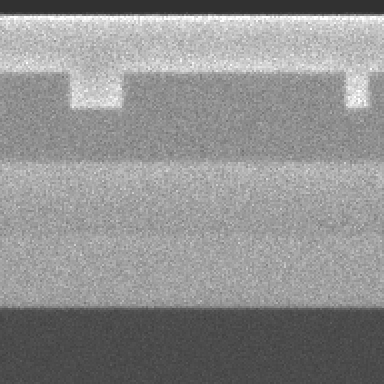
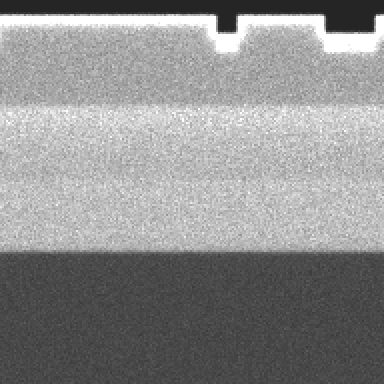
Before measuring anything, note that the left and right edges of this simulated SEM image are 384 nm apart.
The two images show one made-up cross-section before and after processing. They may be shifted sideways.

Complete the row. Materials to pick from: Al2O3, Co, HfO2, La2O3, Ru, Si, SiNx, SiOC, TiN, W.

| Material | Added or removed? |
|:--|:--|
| W | removed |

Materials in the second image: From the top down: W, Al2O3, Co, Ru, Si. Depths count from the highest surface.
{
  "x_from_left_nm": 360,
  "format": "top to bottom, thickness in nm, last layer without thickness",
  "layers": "empty 18, W 18, Al2O3 54, Co 74, Ru 72, Si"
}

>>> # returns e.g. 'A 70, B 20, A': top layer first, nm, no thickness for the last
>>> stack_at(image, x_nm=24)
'Al2O3 90, Co 74, Ru 72, Si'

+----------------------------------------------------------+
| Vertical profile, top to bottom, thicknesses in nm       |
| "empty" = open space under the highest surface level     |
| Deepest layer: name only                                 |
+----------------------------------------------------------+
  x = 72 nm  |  Al2O3 90, Co 74, Ru 72, Si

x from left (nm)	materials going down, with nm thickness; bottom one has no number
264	Al2O3 90, Co 74, Ru 72, Si